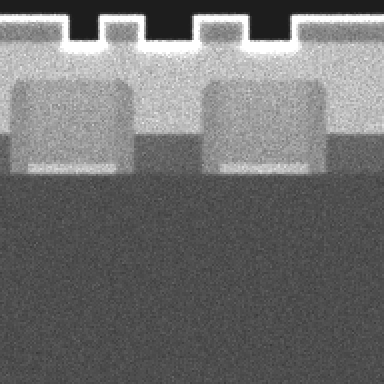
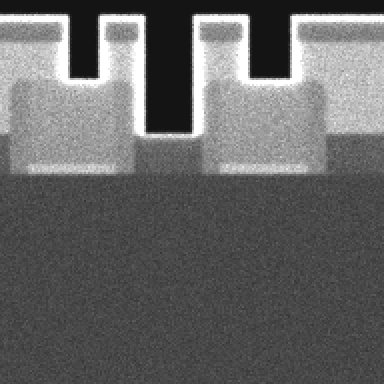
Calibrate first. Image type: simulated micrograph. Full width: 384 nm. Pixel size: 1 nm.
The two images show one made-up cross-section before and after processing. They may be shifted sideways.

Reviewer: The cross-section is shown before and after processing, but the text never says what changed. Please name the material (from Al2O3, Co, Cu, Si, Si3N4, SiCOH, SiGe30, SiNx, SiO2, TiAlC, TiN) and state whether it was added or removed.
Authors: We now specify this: SiO2, removed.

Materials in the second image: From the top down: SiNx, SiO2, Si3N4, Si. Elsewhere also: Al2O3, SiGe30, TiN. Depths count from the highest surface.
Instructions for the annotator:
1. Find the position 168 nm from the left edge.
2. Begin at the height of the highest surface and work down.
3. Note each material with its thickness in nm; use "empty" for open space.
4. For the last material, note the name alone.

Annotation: empty 118, SiGe30 40, Si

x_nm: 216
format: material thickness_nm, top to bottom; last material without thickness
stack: SiNx 26, SiO2 38, Si3N4 94, Si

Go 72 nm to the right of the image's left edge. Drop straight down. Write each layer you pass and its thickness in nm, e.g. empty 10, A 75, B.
empty 64, TiN 84, Al2O3 10, Si